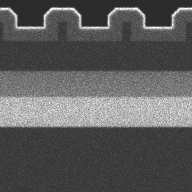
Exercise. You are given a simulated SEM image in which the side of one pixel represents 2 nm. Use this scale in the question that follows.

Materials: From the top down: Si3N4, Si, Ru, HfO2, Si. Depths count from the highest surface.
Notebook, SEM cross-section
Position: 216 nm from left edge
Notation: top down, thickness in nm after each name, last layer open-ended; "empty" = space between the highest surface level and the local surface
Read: empty 14, Si3N4 52, Si 60, Ru 52, HfO2 60, Si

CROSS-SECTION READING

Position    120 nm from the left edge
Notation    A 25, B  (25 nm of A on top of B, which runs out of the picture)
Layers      Si3N4 28, Si 98, Ru 52, HfO2 60, Si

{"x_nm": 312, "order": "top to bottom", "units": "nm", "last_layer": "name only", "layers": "empty 38, Si3N4 28, Si 60, Ru 52, HfO2 60, Si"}